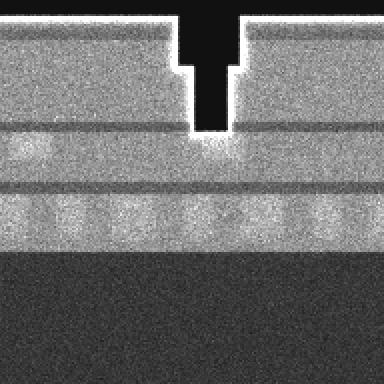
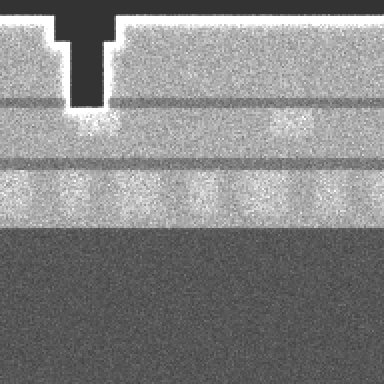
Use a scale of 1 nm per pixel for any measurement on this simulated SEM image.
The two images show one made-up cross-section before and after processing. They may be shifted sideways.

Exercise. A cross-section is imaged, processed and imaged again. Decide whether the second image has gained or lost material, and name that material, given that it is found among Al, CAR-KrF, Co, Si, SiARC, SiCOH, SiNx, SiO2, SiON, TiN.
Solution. removed: SiARC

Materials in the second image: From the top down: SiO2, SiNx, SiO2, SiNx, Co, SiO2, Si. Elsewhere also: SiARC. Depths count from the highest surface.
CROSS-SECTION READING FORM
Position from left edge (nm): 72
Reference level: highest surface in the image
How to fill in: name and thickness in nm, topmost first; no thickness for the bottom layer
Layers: empty 92, SiO2 50, SiNx 12, Co 46, SiO2 12, Si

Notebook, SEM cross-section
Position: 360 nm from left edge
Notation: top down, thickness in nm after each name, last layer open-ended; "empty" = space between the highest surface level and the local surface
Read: SiO2 82, SiNx 10, SiO2 50, SiNx 12, SiO2 58, Si